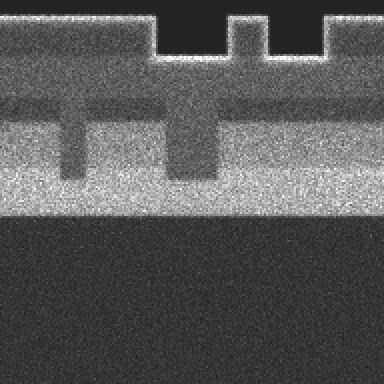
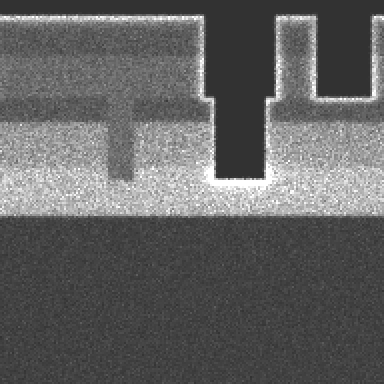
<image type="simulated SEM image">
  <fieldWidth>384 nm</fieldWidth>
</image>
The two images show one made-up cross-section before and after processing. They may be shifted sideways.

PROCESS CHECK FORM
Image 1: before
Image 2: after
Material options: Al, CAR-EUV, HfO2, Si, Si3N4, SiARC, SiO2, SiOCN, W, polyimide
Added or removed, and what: removed, SiO2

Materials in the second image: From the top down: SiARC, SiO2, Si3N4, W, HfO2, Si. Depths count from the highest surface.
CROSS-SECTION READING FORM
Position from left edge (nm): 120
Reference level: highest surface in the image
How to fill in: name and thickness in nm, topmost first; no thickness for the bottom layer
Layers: SiARC 40, SiO2 124, HfO2 36, Si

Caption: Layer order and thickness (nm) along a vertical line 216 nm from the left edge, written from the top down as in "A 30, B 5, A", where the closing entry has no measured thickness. empty 164, HfO2 36, Si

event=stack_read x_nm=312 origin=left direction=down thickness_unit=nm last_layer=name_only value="SiARC 40, SiO2 42, Si3N4 24, W 46, HfO2 48, Si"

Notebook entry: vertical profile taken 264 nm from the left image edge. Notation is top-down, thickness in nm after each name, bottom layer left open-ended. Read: empty 164, HfO2 36, Si